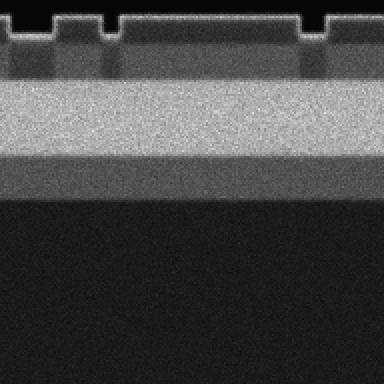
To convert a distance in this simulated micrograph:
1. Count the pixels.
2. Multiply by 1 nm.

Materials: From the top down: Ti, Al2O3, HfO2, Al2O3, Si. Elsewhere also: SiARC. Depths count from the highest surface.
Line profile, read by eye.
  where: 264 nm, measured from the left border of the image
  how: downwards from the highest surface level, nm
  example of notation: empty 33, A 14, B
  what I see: Ti 28, Al2O3 36, HfO2 76, Al2O3 44, Si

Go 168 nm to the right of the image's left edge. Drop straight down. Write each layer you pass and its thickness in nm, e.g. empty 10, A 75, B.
Ti 28, Al2O3 36, HfO2 76, Al2O3 44, Si